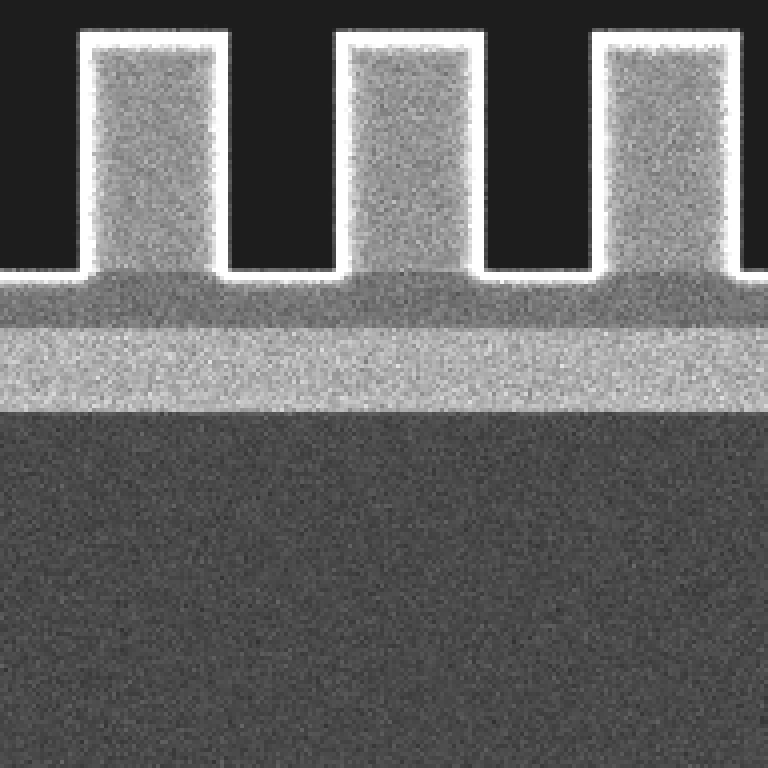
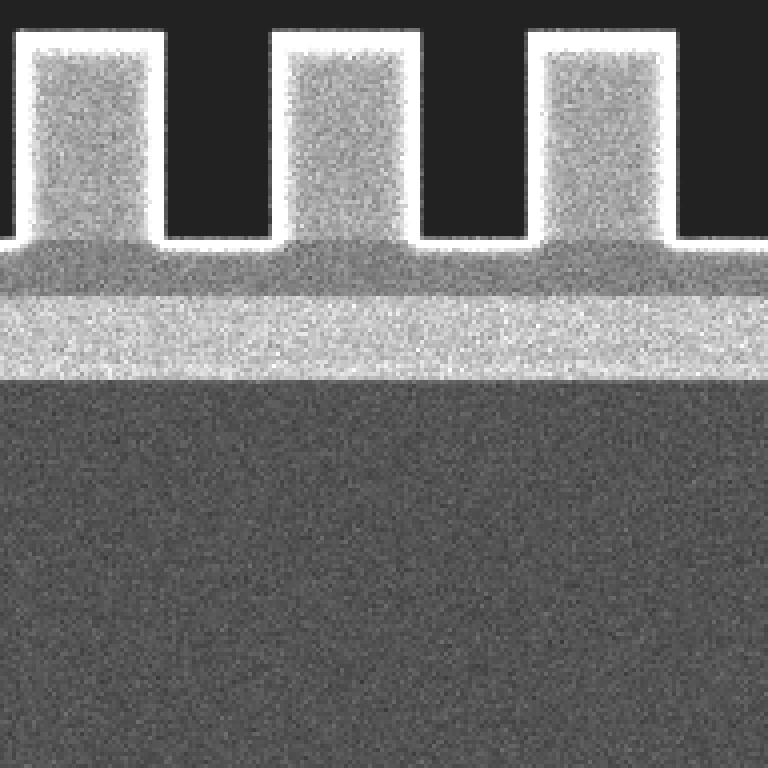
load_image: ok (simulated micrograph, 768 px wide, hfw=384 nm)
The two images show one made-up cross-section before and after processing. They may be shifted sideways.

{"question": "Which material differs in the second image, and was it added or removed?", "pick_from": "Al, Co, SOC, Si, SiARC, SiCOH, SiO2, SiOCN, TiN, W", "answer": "SiARC, removed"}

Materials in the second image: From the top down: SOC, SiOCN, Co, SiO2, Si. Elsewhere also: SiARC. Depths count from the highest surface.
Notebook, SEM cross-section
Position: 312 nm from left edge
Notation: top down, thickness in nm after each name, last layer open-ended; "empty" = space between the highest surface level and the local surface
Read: SOC 104, SiOCN 28, Co 34, SiO2 8, Si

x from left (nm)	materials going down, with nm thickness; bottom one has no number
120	empty 104, SiOCN 28, Co 34, SiO2 8, Si